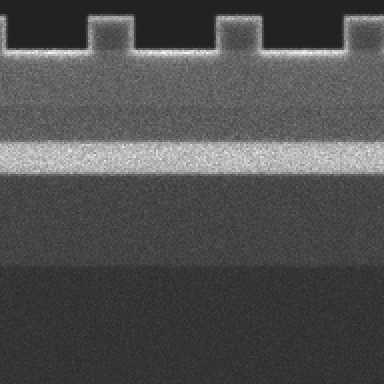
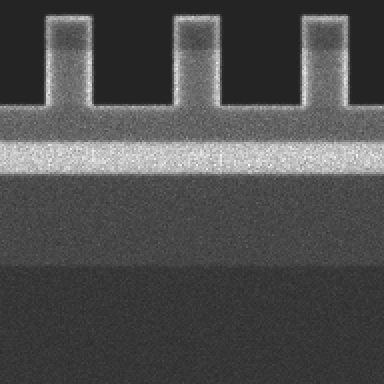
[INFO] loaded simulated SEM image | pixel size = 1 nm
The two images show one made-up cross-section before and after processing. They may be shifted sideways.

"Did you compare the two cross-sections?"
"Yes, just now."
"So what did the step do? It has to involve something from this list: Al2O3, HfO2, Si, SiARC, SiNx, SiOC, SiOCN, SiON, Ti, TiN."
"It removed Al2O3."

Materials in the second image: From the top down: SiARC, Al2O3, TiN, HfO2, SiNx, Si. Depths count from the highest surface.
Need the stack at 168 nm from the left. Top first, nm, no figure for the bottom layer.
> empty 90, TiN 36, HfO2 32, SiNx 92, Si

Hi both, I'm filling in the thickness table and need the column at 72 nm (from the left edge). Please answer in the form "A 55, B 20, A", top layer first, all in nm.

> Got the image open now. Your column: SiARC 34, Al2O3 56, TiN 36, HfO2 32, SiNx 92, Si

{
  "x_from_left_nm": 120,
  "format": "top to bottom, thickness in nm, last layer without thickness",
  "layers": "empty 90, TiN 36, HfO2 32, SiNx 92, Si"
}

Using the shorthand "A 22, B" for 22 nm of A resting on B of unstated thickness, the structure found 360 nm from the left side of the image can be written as empty 90, TiN 36, HfO2 32, SiNx 92, Si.